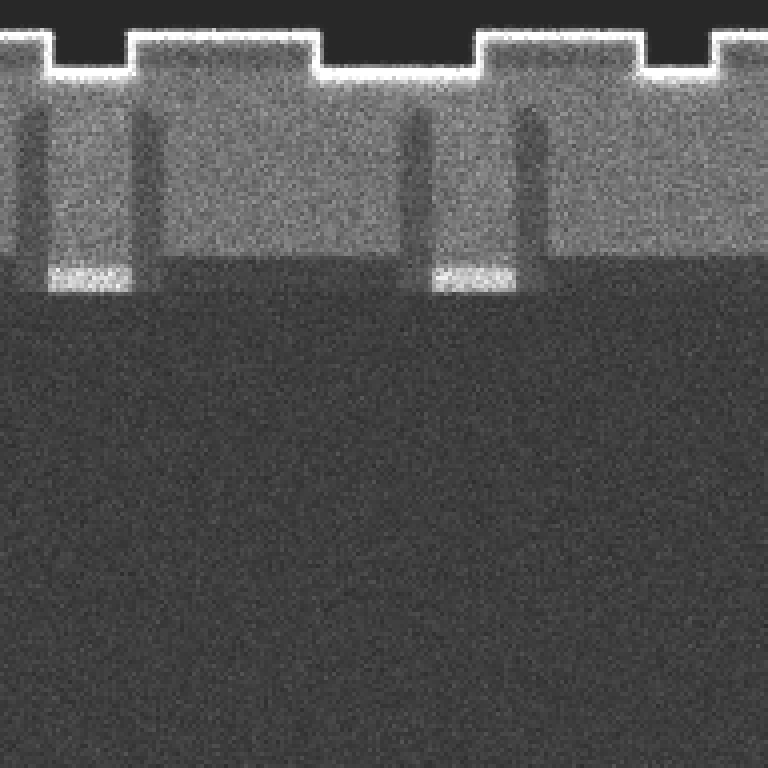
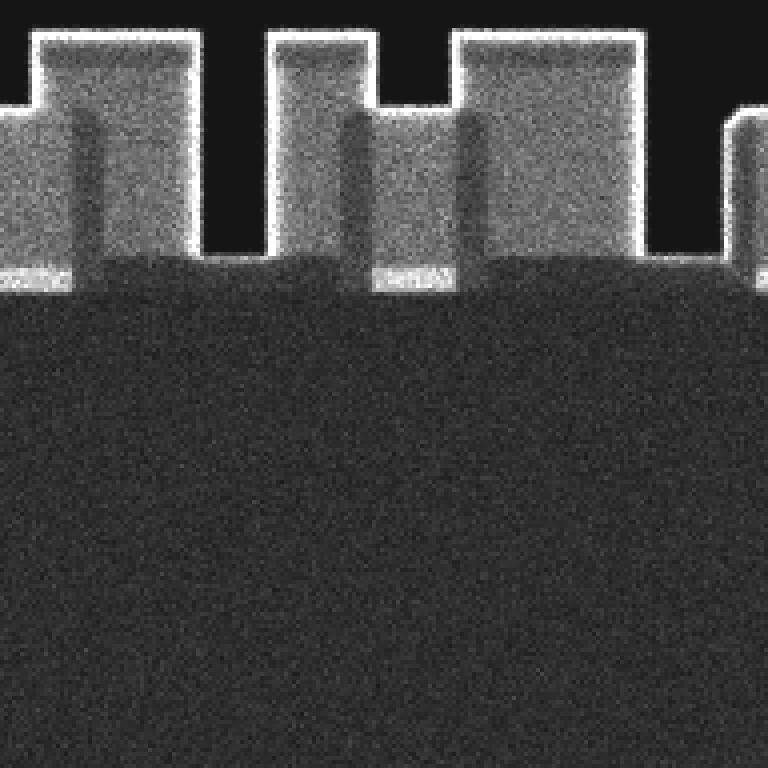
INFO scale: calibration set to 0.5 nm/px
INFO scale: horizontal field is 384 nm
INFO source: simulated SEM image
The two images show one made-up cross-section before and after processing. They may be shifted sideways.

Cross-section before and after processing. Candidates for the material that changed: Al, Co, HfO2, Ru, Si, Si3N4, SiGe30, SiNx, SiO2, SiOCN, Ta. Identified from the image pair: SiO2 (removed).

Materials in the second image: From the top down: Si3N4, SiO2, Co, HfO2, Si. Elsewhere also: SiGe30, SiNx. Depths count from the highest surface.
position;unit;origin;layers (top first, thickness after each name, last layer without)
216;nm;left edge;empty 38, Co 80, HfO2 12, Si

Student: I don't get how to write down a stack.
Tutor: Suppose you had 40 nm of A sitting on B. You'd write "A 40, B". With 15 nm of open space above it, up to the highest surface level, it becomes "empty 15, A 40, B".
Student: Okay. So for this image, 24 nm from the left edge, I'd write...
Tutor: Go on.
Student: Si3N4 18, SiO2 20, Co 80, HfO2 12, Si